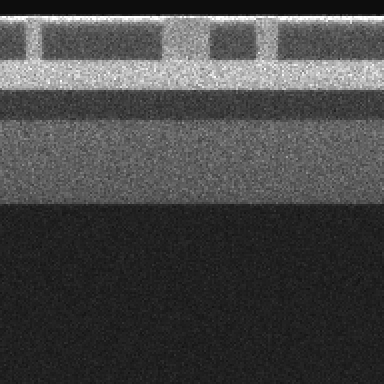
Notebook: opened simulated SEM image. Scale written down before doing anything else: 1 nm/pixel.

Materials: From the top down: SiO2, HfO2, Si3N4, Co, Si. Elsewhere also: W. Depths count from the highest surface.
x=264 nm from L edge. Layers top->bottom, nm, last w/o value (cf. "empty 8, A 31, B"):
W 44, HfO2 30, Si3N4 30, Co 84, Si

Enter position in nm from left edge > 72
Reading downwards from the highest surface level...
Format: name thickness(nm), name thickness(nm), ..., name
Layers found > SiO2 44, HfO2 30, Si3N4 30, Co 84, Si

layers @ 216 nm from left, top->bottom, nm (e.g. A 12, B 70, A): SiO2 44, HfO2 30, Si3N4 30, Co 84, Si